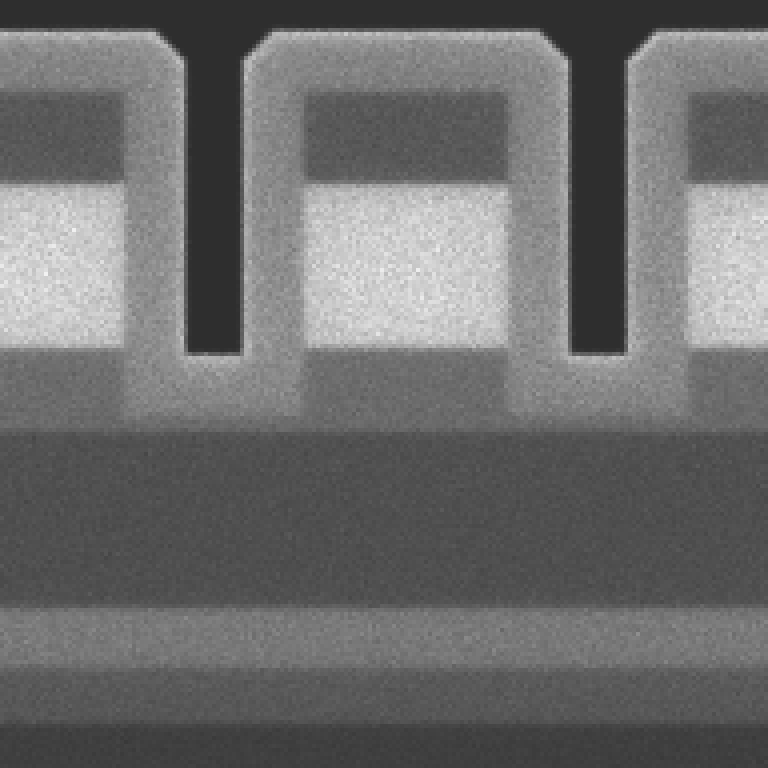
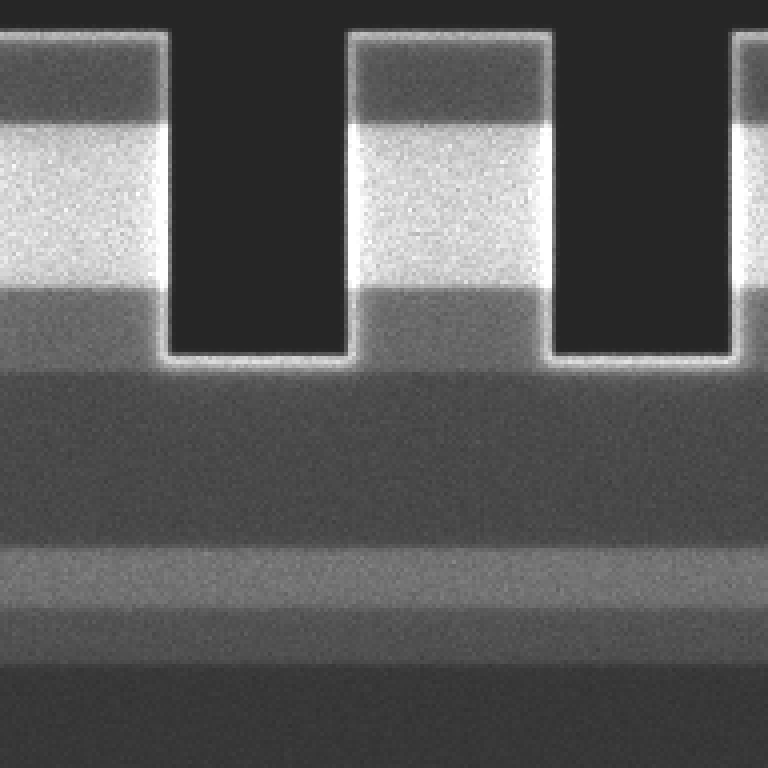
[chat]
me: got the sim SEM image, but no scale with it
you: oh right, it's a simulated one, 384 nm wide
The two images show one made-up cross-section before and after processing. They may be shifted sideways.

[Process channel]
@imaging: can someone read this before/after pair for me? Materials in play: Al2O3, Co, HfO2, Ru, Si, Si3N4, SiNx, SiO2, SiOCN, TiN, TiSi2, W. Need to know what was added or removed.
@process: Co removed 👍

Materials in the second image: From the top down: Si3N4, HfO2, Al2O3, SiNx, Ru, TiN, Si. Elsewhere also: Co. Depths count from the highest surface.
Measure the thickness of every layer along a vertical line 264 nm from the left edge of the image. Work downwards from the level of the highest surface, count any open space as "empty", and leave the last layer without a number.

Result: Si3N4 46, HfO2 82, Al2O3 42, SiNx 88, Ru 30, TiN 28, Si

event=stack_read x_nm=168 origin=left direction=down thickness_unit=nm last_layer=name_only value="empty 162, Al2O3 8, SiNx 88, Ru 30, TiN 28, Si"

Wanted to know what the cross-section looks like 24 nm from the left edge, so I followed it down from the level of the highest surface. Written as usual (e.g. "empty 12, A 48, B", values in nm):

Si3N4 46, HfO2 82, Al2O3 42, SiNx 88, Ru 30, TiN 28, Si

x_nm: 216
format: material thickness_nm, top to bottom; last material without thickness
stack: Si3N4 46, HfO2 82, Al2O3 42, SiNx 88, Ru 30, TiN 28, Si